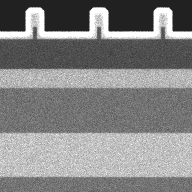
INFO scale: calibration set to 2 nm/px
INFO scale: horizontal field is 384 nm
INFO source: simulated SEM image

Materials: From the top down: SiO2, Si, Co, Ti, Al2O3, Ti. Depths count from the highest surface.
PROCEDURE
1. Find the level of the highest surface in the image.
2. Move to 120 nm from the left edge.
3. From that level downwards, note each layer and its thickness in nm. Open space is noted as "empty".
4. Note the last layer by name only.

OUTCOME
empty 48, SiO2 14, Si 60, Co 38, Ti 90, Al2O3 88, Ti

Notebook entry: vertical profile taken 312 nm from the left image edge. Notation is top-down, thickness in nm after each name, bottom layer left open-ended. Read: empty 2, SiO2 60, Si 60, Co 38, Ti 90, Al2O3 88, Ti